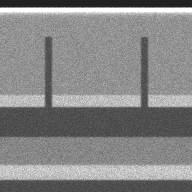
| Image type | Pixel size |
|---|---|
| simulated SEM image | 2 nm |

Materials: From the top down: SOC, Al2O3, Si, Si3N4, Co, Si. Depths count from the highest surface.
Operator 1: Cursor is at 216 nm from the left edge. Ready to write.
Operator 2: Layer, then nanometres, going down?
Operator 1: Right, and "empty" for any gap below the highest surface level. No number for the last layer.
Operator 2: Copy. SOC 174, Al2O3 24, Si 60, Si3N4 56, Co 30, Si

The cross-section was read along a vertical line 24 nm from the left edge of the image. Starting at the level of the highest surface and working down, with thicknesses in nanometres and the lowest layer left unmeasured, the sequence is SOC 174, Al2O3 24, Si 60, Si3N4 56, Co 30, Si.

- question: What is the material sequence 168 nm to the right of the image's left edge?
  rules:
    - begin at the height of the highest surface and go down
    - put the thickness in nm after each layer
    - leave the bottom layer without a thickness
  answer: SOC 174, Al2O3 24, Si 60, Si3N4 56, Co 30, Si